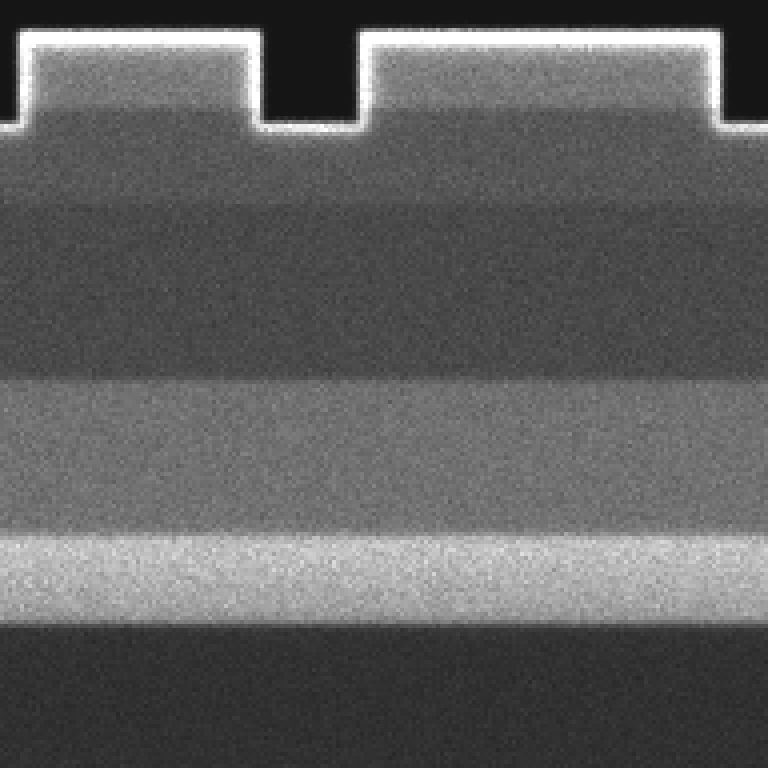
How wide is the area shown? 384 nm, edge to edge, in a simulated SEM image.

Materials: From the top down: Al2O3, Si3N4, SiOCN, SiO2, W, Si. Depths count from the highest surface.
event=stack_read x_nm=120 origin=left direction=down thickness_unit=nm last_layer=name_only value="Al2O3 38, Si3N4 48, SiOCN 88, SiO2 78, W 44, Si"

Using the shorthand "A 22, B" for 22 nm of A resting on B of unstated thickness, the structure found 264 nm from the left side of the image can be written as Al2O3 38, Si3N4 48, SiOCN 88, SiO2 78, W 44, Si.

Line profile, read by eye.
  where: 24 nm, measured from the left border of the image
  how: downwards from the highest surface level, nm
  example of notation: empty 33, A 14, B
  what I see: Al2O3 38, Si3N4 48, SiOCN 88, SiO2 78, W 44, Si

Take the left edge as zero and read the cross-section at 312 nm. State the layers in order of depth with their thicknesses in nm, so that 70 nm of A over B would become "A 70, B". Al2O3 38, Si3N4 48, SiOCN 88, SiO2 78, W 44, Si